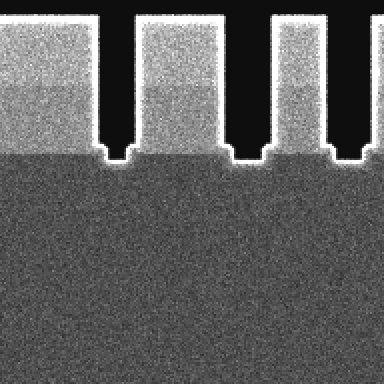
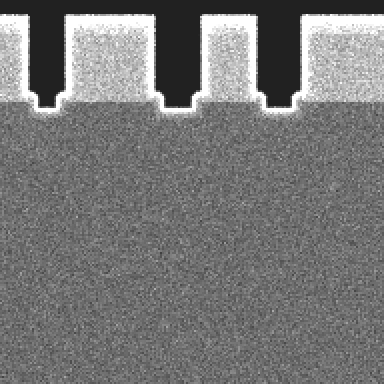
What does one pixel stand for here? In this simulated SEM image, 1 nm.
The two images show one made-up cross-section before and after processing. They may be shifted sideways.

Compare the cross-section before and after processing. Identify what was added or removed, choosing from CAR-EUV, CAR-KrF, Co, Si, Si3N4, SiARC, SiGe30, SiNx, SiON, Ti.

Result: Si3N4 removed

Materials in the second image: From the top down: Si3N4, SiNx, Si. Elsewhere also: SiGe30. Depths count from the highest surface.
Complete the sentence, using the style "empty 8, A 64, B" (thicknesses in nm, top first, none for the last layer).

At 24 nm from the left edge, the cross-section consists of Si3N4 18, SiNx 68, Si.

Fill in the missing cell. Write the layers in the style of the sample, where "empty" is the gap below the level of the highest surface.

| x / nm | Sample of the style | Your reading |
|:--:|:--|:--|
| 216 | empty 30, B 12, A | Si3N4 18, SiNx 68, Si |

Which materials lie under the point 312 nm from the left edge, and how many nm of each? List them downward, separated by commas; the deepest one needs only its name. Si3N4 18, SiNx 68, Si